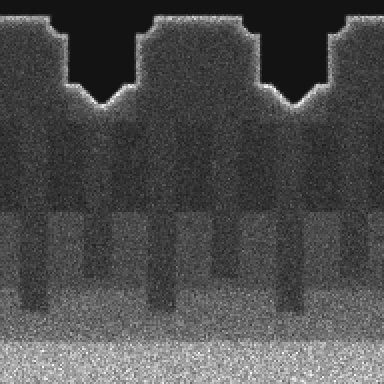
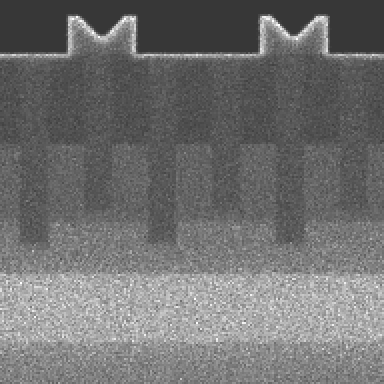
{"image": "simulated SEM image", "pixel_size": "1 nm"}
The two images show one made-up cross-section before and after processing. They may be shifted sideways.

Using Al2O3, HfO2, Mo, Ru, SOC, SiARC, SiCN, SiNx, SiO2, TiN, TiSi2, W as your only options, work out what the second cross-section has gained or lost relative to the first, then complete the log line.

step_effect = removed SOC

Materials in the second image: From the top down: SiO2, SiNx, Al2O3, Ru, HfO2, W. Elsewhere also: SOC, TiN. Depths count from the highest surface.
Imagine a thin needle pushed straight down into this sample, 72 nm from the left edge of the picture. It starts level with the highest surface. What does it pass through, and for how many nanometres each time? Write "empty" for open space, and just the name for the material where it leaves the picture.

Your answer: SiO2 38, SiNx 90, Al2O3 78, Ru 52, HfO2 68, W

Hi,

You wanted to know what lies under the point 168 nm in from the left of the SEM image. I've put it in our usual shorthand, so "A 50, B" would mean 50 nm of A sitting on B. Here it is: empty 38, TiN 190, Ru 30, HfO2 68, W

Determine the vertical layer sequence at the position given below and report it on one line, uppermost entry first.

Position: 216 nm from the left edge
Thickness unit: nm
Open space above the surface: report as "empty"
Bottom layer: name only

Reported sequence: empty 38, TiN 156, Al2O3 12, Ru 52, HfO2 68, W